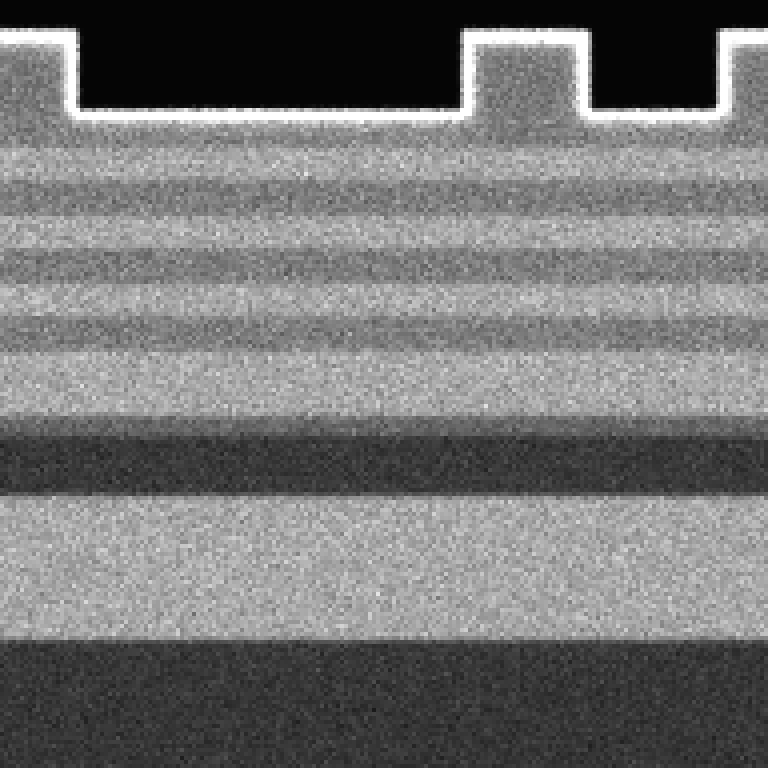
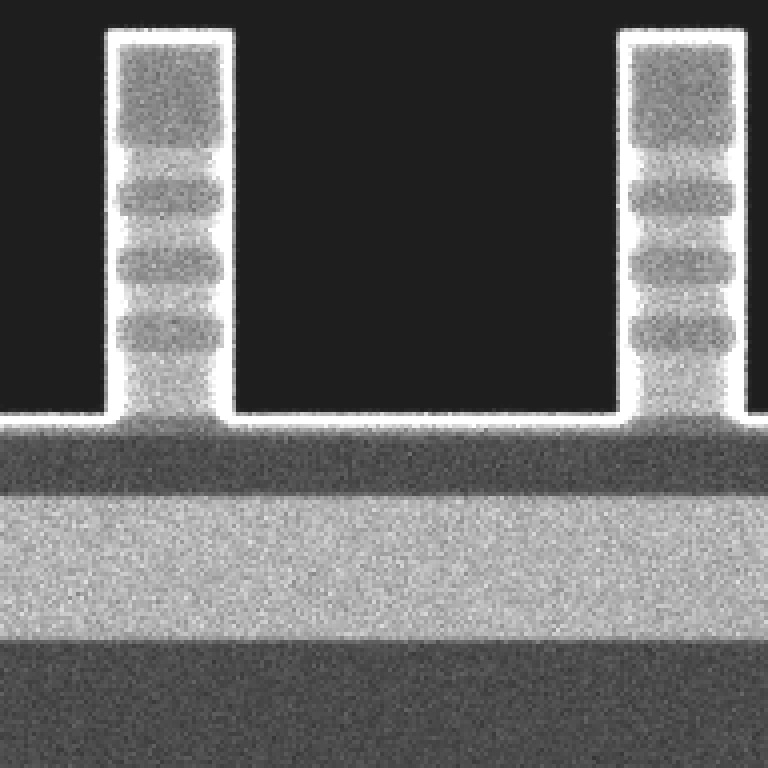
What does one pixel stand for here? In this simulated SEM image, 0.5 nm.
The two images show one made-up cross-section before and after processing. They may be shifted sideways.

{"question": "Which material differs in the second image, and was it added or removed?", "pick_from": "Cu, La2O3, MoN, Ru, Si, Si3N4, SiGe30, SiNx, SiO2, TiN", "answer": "SiO2 and TiN, removed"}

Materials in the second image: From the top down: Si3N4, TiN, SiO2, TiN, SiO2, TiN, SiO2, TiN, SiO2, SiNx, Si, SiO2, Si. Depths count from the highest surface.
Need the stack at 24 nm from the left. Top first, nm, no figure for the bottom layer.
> empty 192, SiNx 10, Si 30, SiO2 72, Si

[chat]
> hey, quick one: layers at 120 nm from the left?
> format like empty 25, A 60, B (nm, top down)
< empty 192, SiNx 10, Si 30, SiO2 72, Si